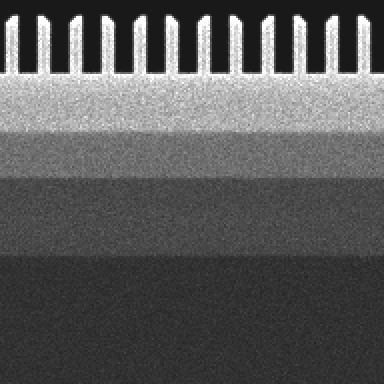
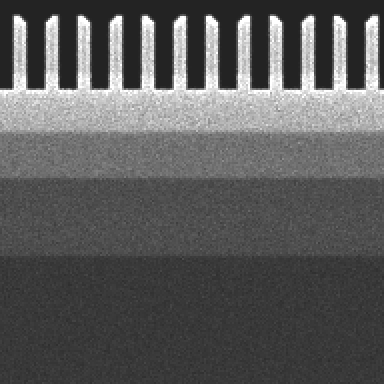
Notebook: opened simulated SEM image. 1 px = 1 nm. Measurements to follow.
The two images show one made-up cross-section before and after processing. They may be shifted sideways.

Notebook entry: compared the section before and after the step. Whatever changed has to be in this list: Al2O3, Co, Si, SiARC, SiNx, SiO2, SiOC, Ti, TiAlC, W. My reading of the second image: W removed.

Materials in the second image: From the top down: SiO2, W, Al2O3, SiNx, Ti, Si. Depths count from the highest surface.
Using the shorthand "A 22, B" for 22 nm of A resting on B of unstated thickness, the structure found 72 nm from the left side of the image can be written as empty 74, W 42, Al2O3 46, SiNx 30, Ti 48, Si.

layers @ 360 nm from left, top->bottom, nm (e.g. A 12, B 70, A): empty 74, W 42, Al2O3 46, SiNx 30, Ti 48, Si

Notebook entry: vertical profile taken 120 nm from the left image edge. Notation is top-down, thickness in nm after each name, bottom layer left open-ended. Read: SiO2 58, W 58, Al2O3 46, SiNx 30, Ti 48, Si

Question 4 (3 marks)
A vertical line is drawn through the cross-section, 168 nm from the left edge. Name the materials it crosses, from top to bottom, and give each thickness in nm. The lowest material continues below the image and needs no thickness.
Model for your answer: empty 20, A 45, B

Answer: empty 74, W 42, Al2O3 46, SiNx 30, Ti 48, Si